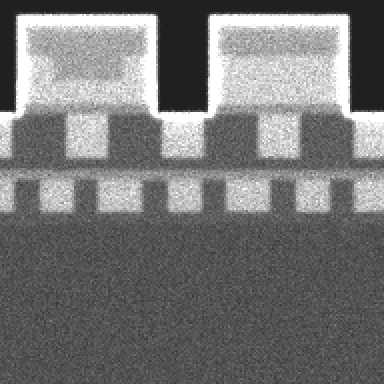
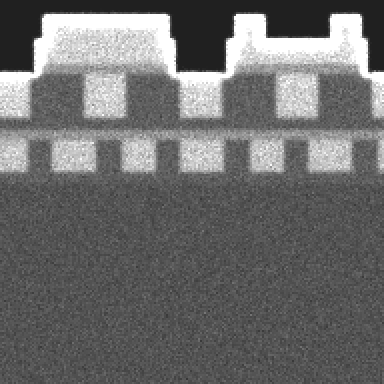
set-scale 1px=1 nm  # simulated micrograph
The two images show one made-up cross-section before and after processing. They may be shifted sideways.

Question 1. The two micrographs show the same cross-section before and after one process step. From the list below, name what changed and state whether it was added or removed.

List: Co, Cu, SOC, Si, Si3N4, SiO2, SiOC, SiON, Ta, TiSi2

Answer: SOC, removed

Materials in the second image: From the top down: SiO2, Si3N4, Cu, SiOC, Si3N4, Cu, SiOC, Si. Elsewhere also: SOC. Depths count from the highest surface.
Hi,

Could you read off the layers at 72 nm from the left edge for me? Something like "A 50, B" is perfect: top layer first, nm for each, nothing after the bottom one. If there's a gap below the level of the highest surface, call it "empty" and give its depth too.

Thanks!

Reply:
SiO2 48, Si3N4 10, SiOC 56, Si3N4 10, Cu 32, SiOC 12, Si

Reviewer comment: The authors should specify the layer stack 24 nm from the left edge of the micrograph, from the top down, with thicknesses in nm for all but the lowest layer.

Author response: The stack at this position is empty 58, Cu 44, SiOC 12, Si3N4 10, Cu 32, SiOC 12, Si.